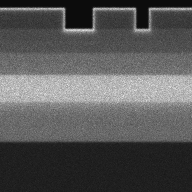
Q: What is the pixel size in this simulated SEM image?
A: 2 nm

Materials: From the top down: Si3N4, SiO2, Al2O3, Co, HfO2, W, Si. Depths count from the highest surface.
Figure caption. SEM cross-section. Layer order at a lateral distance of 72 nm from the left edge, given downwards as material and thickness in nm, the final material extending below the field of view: Si3N4 42, SiO2 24, Al2O3 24, Co 44, HfO2 54, W 80, Si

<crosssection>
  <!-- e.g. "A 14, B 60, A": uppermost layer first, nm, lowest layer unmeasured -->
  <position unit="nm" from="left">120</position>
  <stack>Si3N4 42, SiO2 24, Al2O3 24, Co 44, HfO2 54, W 80, Si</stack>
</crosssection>